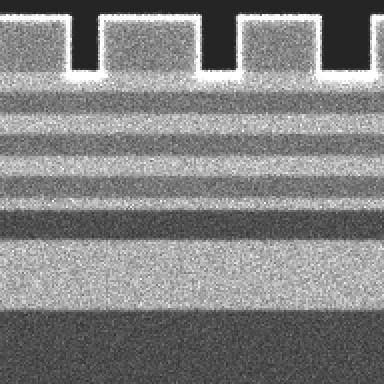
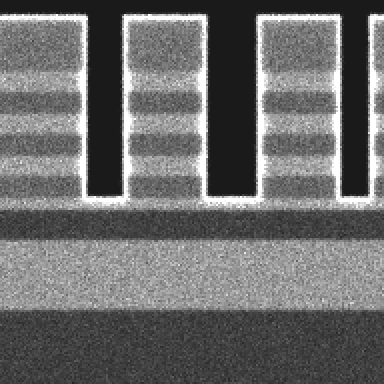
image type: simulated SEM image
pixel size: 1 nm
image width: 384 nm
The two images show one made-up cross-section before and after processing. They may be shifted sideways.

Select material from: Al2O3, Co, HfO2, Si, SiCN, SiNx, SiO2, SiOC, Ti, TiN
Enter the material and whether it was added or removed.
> Al2O3 and SiNx / removed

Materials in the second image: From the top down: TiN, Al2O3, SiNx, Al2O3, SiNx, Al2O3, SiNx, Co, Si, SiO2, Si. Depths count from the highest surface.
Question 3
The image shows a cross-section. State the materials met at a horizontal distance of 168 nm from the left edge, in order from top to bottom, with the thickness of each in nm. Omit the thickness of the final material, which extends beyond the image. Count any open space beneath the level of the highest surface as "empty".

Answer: TiN 56, Al2O3 20, SiNx 22, Al2O3 20, SiNx 22, Al2O3 20, SiNx 22, Co 12, Si 30, SiO2 70, Si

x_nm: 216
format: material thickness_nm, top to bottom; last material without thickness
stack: empty 182, Co 12, Si 30, SiO2 70, Si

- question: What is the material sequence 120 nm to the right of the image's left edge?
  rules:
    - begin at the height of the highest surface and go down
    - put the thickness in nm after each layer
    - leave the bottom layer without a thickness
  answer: empty 182, Co 12, Si 30, SiO2 70, Si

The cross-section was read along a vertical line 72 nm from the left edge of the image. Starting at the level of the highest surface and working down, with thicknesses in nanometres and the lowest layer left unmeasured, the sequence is TiN 56, Al2O3 20, SiNx 22, Al2O3 20, SiNx 22, Al2O3 20, SiNx 22, Co 12, Si 30, SiO2 70, Si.